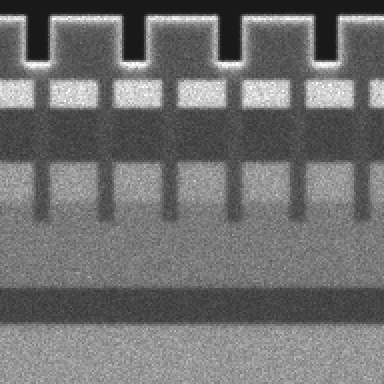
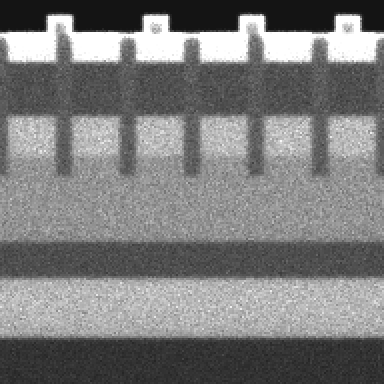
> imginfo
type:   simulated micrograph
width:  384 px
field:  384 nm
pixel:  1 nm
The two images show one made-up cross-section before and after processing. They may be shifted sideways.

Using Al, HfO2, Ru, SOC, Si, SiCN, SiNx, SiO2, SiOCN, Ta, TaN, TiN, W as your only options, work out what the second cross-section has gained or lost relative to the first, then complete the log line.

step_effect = removed SOC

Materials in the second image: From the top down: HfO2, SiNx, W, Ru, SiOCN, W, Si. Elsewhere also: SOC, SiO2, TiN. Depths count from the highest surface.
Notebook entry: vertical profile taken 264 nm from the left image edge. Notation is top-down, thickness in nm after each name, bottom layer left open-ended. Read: empty 18, HfO2 28, SiNx 54, W 40, Ru 86, SiOCN 36, W 60, Si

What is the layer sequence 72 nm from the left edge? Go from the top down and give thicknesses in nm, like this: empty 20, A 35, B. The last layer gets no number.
empty 18, HfO2 28, SiNx 54, W 40, Ru 86, SiOCN 36, W 60, Si